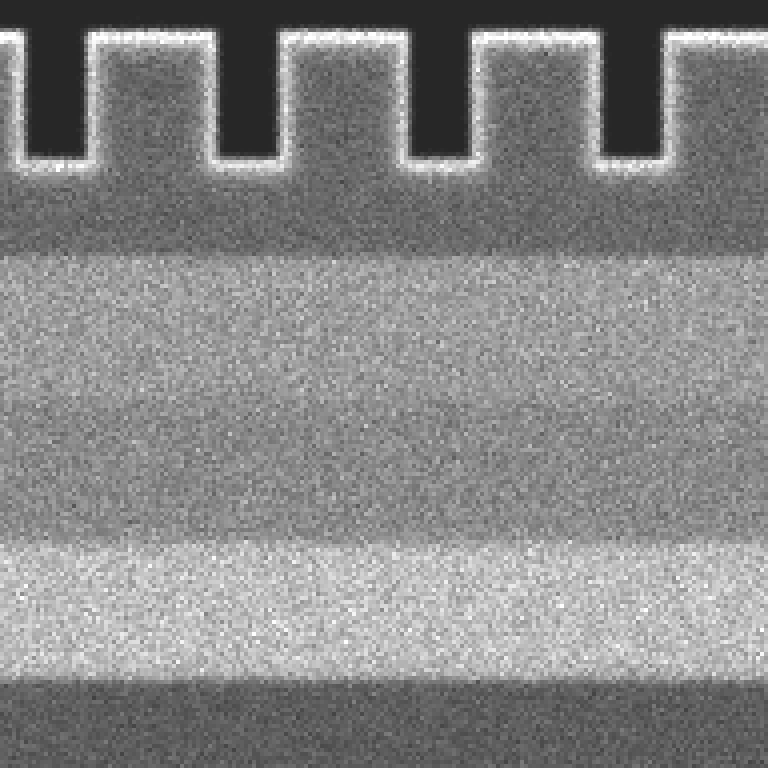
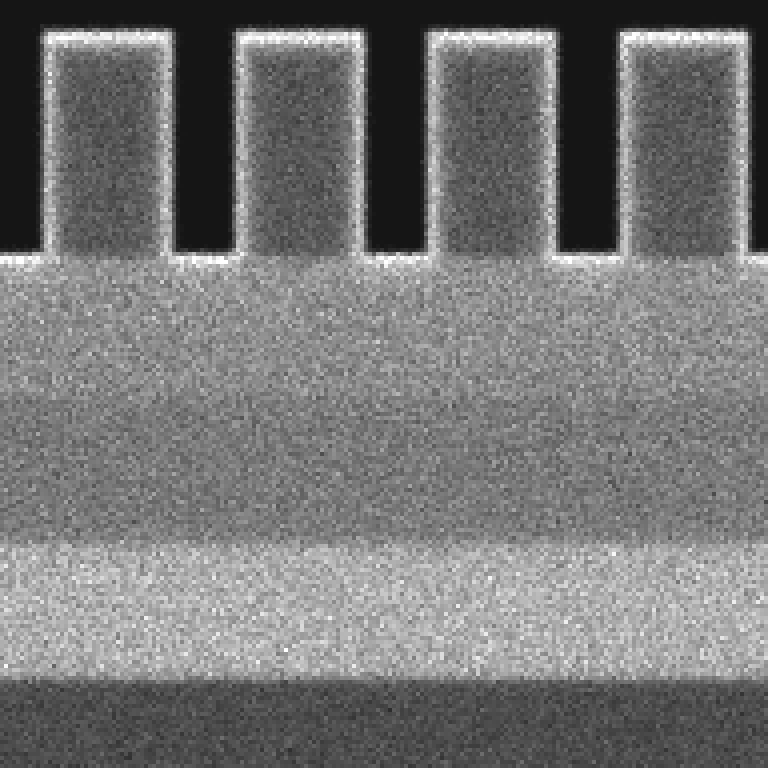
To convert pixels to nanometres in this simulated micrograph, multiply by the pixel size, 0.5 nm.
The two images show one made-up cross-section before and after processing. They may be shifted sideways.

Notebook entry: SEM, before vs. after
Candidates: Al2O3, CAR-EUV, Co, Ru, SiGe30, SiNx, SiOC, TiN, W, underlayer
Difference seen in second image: underlayer removed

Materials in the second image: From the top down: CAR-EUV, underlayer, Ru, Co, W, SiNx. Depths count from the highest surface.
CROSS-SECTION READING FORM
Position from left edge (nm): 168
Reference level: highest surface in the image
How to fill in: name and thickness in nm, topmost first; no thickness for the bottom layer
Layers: CAR-EUV 64, underlayer 48, Ru 72, Co 72, W 68, SiNx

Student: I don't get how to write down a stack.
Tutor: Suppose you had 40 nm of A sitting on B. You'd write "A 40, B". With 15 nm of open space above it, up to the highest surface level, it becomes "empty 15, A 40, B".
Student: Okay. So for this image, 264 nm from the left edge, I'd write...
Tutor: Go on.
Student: CAR-EUV 64, underlayer 48, Ru 72, Co 72, W 68, SiNx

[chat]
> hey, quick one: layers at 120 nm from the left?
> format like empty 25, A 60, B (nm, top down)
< CAR-EUV 64, underlayer 48, Ru 72, Co 72, W 68, SiNx